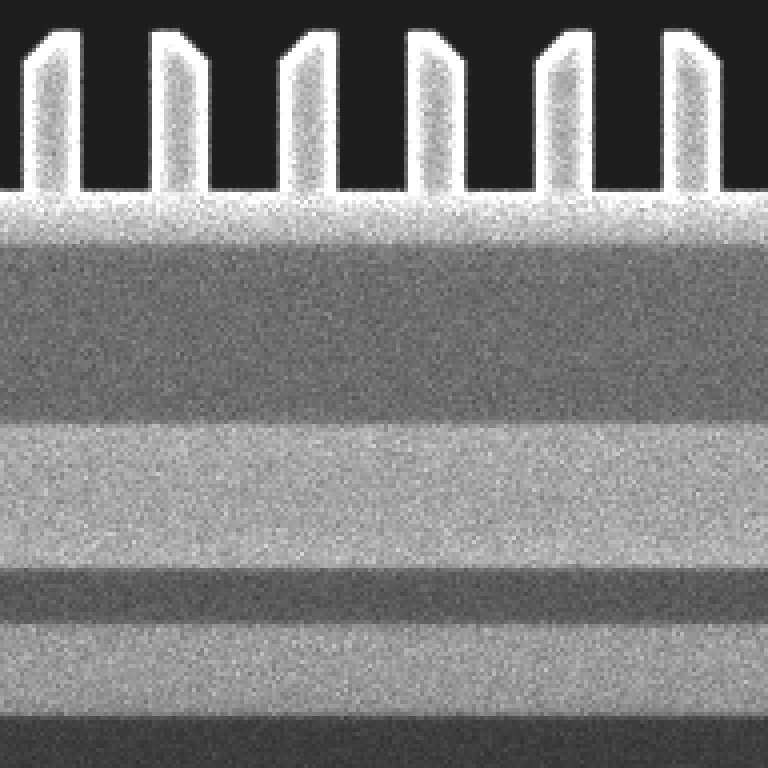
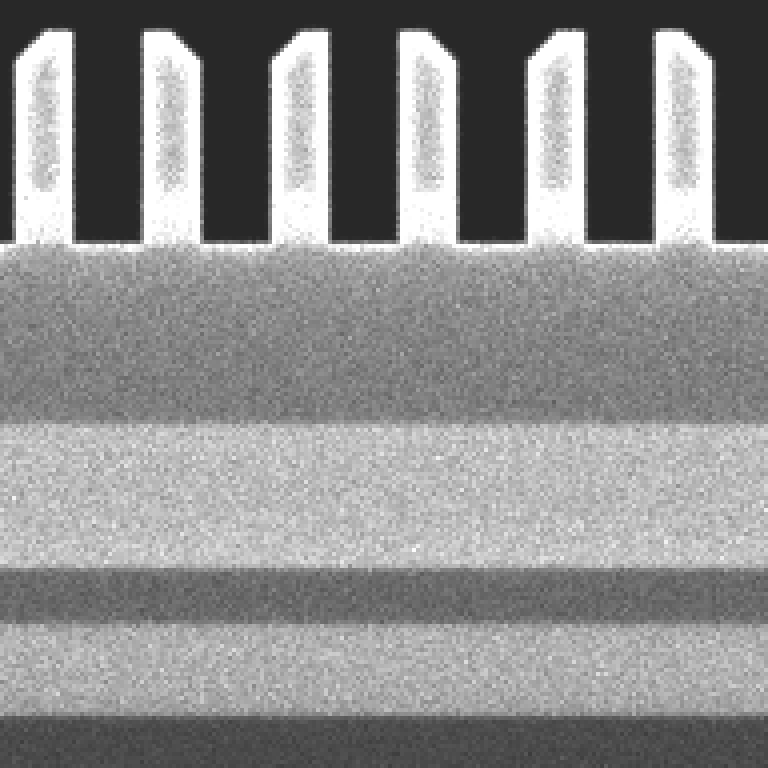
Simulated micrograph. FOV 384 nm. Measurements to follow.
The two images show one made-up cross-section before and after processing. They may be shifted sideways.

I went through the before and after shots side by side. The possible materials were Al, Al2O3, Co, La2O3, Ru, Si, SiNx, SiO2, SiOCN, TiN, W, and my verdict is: removed, Ru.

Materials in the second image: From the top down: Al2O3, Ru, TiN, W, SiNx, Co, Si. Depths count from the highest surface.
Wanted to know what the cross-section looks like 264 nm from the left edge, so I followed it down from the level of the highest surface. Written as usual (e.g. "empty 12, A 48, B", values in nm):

empty 14, Al2O3 66, Ru 26, TiN 90, W 72, SiNx 28, Co 46, Si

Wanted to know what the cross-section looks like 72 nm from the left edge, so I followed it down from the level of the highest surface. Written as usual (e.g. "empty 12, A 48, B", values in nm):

Al2O3 80, Ru 26, TiN 90, W 72, SiNx 28, Co 46, Si